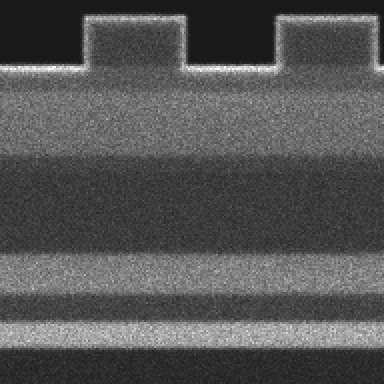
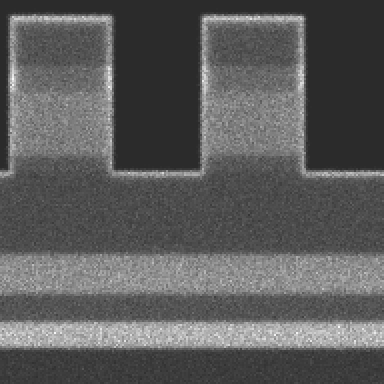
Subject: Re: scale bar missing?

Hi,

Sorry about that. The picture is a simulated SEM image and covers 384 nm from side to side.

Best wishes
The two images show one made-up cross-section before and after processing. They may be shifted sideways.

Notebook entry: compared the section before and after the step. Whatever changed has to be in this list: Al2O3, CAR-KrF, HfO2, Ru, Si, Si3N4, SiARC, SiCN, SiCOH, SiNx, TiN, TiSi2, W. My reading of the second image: Al2O3 and Ru and TiN removed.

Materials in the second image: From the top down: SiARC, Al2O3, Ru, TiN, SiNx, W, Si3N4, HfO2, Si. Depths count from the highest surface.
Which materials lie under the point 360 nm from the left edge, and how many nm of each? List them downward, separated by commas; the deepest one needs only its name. empty 156, SiNx 82, W 40, Si3N4 28, HfO2 26, Si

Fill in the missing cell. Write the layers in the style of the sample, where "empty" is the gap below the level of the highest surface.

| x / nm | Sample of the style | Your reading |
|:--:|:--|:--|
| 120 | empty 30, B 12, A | empty 156, SiNx 82, W 40, Si3N4 28, HfO2 26, Si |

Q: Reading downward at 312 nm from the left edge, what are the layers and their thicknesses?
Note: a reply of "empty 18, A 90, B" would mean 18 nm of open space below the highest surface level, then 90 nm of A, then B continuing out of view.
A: empty 156, SiNx 82, W 40, Si3N4 28, HfO2 26, Si